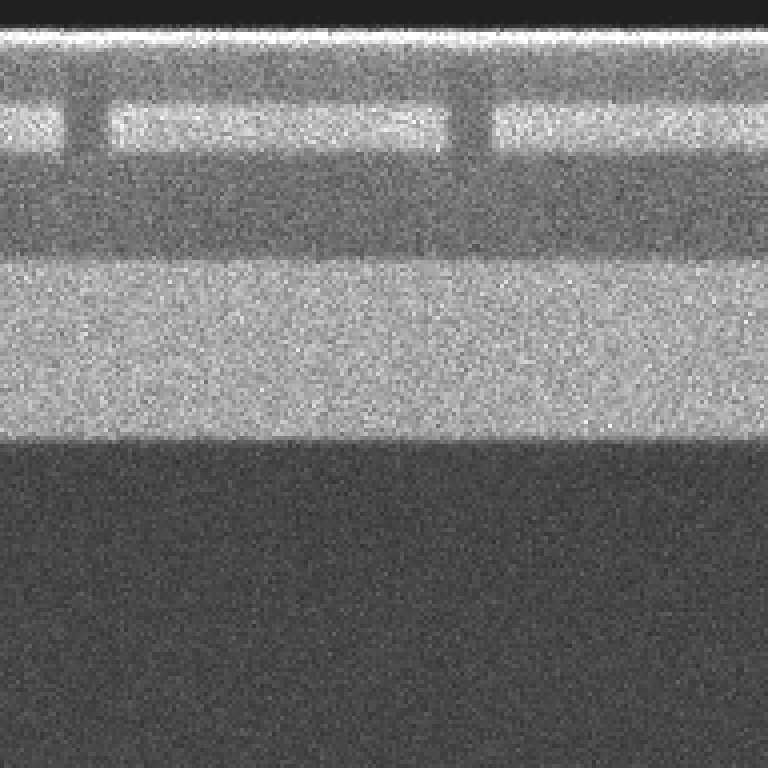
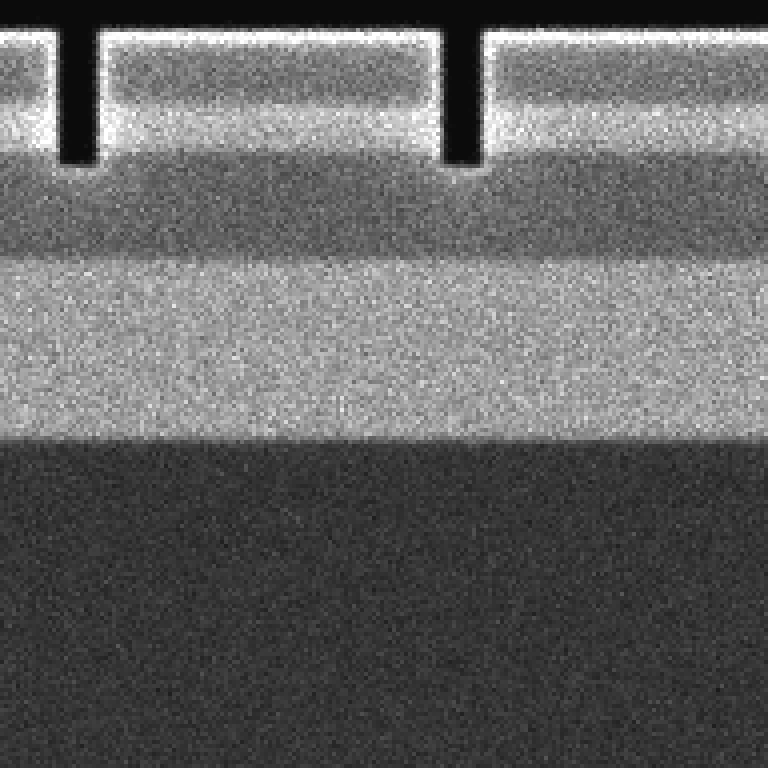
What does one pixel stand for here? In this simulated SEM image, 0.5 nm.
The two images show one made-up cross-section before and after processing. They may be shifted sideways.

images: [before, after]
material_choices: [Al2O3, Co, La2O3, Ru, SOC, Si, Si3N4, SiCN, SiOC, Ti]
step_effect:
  removed: SOC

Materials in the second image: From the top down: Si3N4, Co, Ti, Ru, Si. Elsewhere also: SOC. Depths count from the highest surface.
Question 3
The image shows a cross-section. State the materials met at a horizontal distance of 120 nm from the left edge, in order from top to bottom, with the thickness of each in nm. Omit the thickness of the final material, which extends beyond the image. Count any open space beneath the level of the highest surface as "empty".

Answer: Si3N4 36, Co 24, Ti 54, Ru 90, Si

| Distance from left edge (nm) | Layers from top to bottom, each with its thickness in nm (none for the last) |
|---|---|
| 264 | Si3N4 36, Co 24, Ti 54, Ru 90, Si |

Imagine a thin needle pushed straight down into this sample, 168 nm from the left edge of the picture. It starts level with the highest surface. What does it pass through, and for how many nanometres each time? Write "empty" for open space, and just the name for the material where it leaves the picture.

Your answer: Si3N4 36, Co 24, Ti 54, Ru 90, Si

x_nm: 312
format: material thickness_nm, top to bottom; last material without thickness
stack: Si3N4 36, Co 24, Ti 54, Ru 90, Si